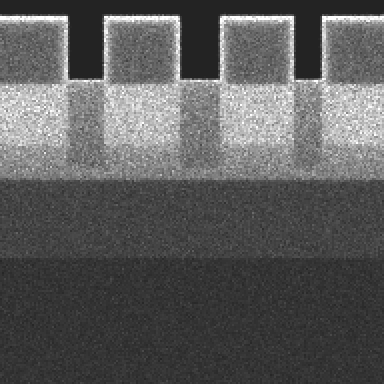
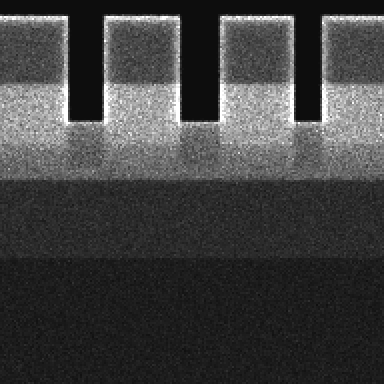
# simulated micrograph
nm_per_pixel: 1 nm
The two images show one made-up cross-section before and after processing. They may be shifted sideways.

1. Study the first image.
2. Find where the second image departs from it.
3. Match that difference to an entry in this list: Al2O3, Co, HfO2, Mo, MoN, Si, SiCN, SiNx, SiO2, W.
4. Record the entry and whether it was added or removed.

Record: Co / removed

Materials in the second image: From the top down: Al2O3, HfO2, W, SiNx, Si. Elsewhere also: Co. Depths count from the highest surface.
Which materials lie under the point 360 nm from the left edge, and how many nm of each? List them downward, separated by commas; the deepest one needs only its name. Al2O3 68, HfO2 60, W 36, SiNx 78, Si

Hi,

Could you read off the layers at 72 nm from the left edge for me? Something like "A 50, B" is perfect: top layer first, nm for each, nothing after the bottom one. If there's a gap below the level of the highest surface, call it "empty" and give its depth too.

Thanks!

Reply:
empty 106, Co 46, W 12, SiNx 78, Si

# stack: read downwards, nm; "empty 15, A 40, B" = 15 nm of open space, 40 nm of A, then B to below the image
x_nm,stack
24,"Al2O3 68, HfO2 60, W 36, SiNx 78, Si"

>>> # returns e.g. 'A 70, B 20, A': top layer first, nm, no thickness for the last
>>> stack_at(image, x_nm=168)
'Al2O3 68, HfO2 60, W 36, SiNx 78, Si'